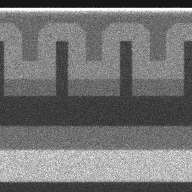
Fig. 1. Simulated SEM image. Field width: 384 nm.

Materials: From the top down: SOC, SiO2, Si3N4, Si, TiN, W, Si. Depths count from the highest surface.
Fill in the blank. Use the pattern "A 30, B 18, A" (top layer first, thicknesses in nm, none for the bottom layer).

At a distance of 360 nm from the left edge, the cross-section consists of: SOC 30, SiO2 112, Si3N4 34, Si 60, TiN 48, W 64, Si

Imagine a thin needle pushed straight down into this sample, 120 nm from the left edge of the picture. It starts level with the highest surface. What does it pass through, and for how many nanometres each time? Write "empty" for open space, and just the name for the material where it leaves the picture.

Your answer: SOC 30, SiO2 36, Si 170, TiN 48, W 64, Si